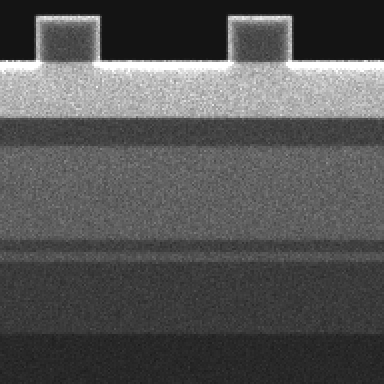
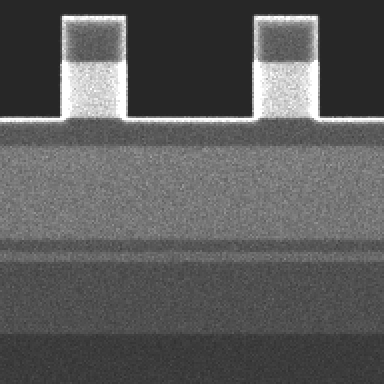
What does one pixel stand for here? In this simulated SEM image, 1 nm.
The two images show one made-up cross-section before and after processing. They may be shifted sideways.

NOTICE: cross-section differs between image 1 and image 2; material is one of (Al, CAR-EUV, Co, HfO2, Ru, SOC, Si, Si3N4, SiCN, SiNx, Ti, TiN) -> removed: HfO2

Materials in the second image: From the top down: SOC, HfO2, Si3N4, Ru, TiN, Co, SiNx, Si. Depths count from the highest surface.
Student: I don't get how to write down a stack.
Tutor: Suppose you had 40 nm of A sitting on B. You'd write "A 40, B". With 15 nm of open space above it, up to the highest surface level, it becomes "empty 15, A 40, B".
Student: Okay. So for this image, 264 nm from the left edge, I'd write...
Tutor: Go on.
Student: SOC 46, HfO2 56, Si3N4 28, Ru 94, TiN 12, Co 10, SiNx 72, Si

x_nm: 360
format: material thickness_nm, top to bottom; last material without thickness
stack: empty 102, Si3N4 28, Ru 94, TiN 12, Co 10, SiNx 72, Si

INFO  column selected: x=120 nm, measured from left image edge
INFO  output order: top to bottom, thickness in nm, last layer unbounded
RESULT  SOC 46, HfO2 56, Si3N4 28, Ru 94, TiN 12, Co 10, SiNx 72, Si